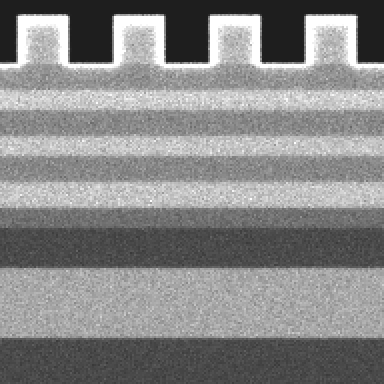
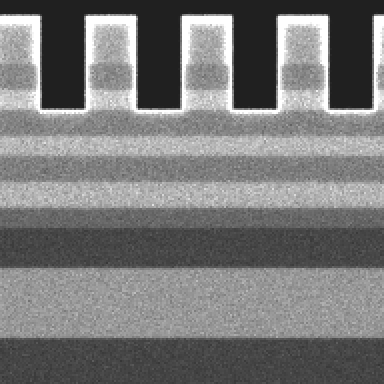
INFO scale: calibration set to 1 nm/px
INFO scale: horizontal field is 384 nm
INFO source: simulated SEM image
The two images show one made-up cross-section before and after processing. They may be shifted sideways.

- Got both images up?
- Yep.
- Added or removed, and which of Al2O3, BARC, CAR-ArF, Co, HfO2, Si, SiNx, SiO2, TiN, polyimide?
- removed, Co and TiN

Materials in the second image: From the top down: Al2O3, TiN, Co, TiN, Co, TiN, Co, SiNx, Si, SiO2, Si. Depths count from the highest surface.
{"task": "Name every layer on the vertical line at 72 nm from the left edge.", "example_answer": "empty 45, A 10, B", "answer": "empty 94, TiN 26, Co 20, TiN 26, Co 26, SiNx 20, Si 40, SiO2 70, Si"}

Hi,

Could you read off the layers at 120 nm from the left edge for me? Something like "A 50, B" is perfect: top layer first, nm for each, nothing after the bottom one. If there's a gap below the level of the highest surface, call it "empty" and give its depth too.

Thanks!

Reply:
Al2O3 48, TiN 26, Co 20, TiN 26, Co 20, TiN 26, Co 26, SiNx 20, Si 40, SiO2 70, Si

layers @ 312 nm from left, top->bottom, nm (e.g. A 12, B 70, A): Al2O3 48, TiN 26, Co 20, TiN 26, Co 20, TiN 26, Co 26, SiNx 20, Si 40, SiO2 70, Si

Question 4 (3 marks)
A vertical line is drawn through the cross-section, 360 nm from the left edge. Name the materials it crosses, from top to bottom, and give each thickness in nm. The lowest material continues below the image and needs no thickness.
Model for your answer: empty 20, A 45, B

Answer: empty 94, TiN 26, Co 20, TiN 26, Co 26, SiNx 20, Si 40, SiO2 70, Si